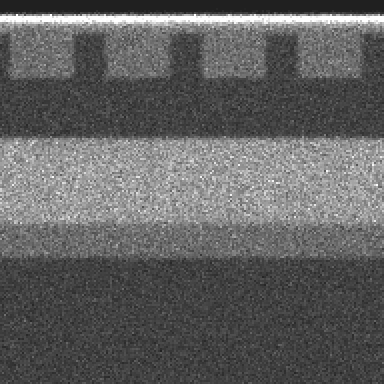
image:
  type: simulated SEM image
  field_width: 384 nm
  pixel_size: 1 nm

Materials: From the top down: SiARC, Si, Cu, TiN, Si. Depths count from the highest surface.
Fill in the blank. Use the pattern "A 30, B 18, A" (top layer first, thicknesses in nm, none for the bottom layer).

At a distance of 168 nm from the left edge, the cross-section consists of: SiARC 62, Si 60, Cu 86, TiN 34, Si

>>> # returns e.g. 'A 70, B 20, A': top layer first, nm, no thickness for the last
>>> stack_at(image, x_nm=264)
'SiARC 62, Si 60, Cu 86, TiN 34, Si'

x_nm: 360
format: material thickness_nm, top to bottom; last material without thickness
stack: SiARC 62, Si 60, Cu 86, TiN 34, Si